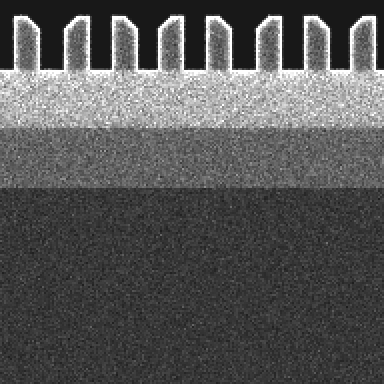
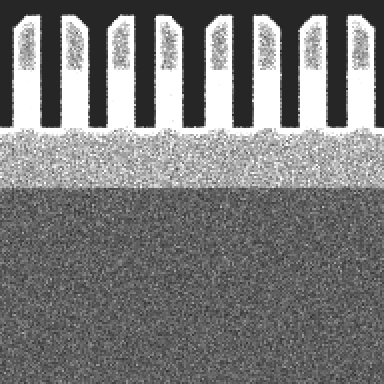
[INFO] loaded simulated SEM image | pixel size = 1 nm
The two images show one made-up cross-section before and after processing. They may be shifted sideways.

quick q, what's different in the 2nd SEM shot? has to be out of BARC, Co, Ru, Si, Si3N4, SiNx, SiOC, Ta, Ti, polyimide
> Ru removed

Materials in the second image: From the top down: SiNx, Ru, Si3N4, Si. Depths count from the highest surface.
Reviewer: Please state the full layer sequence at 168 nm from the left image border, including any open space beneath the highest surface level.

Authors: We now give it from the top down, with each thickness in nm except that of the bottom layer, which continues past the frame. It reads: SiNx 54, Ru 58, Si3N4 60, Si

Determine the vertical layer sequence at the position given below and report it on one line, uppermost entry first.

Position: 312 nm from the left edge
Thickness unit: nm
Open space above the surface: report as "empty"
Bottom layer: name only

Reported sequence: SiNx 54, Ru 58, Si3N4 60, Si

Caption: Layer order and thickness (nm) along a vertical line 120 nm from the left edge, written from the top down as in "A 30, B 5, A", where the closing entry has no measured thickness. SiNx 54, Ru 58, Si3N4 60, Si